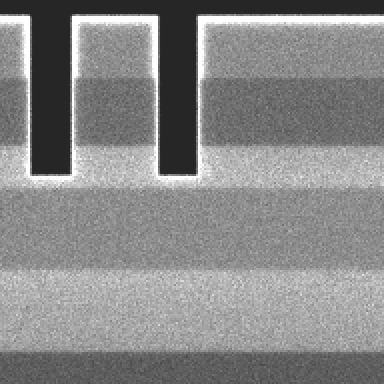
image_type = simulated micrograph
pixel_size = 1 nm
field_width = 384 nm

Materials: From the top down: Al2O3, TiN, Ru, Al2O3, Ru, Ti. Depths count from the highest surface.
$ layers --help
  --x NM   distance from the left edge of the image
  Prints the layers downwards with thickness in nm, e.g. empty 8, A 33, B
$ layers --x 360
Al2O3 62, TiN 68, Ru 42, Al2O3 82, Ru 82, Ti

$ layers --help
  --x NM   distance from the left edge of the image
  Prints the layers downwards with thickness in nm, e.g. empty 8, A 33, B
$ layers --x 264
Al2O3 62, TiN 68, Ru 42, Al2O3 82, Ru 82, Ti